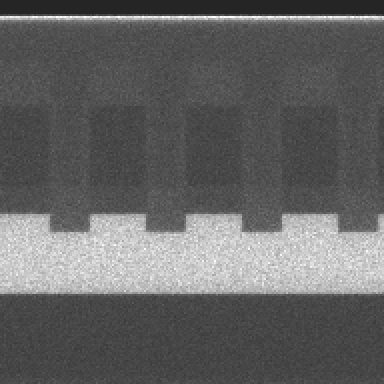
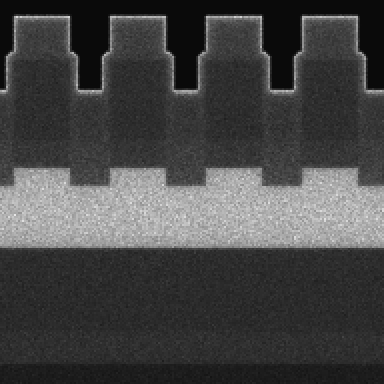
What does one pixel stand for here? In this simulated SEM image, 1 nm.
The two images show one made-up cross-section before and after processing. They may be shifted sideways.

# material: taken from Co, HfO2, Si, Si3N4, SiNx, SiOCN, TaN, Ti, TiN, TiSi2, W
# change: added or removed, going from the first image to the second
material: Si3N4
change: removed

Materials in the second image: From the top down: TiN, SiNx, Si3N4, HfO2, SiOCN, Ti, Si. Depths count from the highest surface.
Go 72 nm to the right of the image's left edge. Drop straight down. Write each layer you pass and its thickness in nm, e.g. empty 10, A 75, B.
empty 36, TiN 134, HfO2 62, SiOCN 84, Ti 32, Si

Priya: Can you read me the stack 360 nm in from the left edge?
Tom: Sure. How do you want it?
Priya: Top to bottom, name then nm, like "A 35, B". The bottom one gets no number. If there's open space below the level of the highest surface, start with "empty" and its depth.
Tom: empty 36, TiN 134, HfO2 62, SiOCN 84, Ti 32, Si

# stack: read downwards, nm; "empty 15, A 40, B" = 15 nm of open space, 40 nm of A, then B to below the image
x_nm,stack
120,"TiN 44, SiNx 80, Si3N4 28, HfO2 80, SiOCN 84, Ti 32, Si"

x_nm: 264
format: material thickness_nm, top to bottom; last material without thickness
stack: empty 36, TiN 134, HfO2 62, SiOCN 84, Ti 32, Si